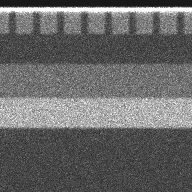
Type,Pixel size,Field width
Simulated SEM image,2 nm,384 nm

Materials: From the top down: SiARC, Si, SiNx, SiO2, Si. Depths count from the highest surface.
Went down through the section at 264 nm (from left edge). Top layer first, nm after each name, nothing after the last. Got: SiARC 6, Si 106, SiNx 68, SiO2 60, Si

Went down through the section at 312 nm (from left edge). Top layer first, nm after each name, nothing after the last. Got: SiARC 6, Si 106, SiNx 68, SiO2 60, Si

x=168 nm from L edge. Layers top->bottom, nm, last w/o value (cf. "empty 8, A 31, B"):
SiARC 6, Si 106, SiNx 68, SiO2 60, Si